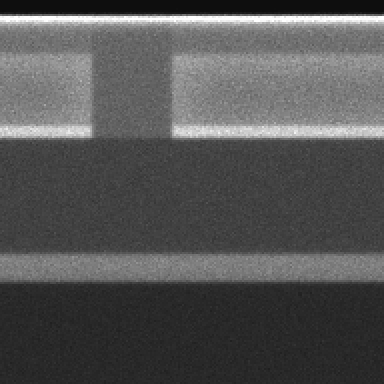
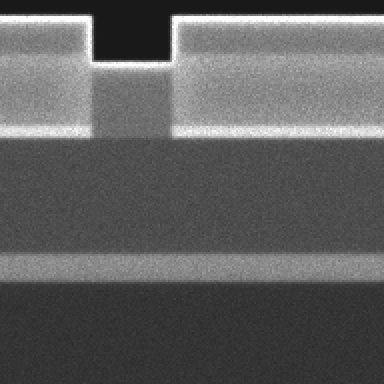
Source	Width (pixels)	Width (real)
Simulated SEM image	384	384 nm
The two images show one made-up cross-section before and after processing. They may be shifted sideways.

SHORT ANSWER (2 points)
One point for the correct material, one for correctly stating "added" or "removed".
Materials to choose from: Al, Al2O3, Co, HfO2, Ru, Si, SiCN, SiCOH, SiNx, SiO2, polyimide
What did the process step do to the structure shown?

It removed SiO2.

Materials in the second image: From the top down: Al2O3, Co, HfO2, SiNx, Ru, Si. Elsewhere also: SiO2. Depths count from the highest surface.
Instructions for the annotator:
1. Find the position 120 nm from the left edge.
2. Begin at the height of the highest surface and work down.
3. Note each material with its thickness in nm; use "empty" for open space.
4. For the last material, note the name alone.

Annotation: empty 46, SiO2 76, SiNx 116, Ru 28, Si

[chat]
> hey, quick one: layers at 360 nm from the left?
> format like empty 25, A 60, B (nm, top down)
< Al2O3 38, Co 72, HfO2 12, SiNx 116, Ru 28, Si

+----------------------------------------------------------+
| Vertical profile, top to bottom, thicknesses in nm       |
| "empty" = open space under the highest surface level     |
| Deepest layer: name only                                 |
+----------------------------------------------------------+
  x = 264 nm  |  Al2O3 38, Co 72, HfO2 12, SiNx 116, Ru 28, Si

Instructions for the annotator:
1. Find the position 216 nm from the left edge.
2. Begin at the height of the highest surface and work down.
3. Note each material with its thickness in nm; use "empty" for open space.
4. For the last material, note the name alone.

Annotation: Al2O3 38, Co 72, HfO2 12, SiNx 116, Ru 28, Si